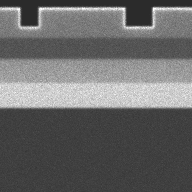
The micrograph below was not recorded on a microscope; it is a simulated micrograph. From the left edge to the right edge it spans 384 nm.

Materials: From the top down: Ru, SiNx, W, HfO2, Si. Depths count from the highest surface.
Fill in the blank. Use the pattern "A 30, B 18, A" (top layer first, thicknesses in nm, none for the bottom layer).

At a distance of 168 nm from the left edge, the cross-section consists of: Ru 60, SiNx 42, W 48, HfO2 50, Si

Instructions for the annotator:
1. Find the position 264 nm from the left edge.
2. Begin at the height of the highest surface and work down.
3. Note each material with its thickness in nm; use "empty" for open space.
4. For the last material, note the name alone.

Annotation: empty 38, Ru 22, SiNx 42, W 48, HfO2 50, Si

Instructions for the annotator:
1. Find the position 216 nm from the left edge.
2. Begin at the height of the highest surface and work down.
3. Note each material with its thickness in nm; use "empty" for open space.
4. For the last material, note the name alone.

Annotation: Ru 60, SiNx 42, W 48, HfO2 50, Si